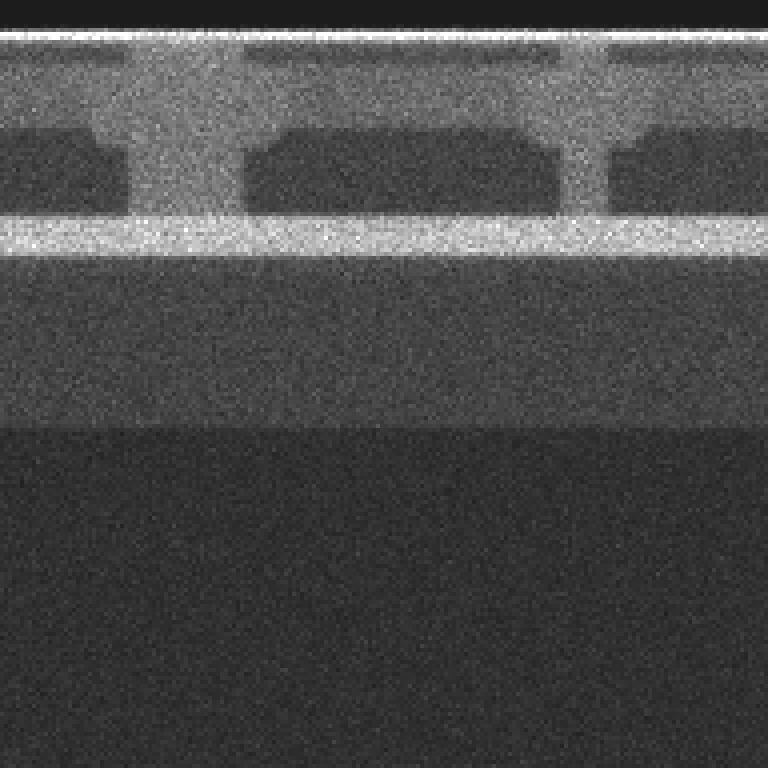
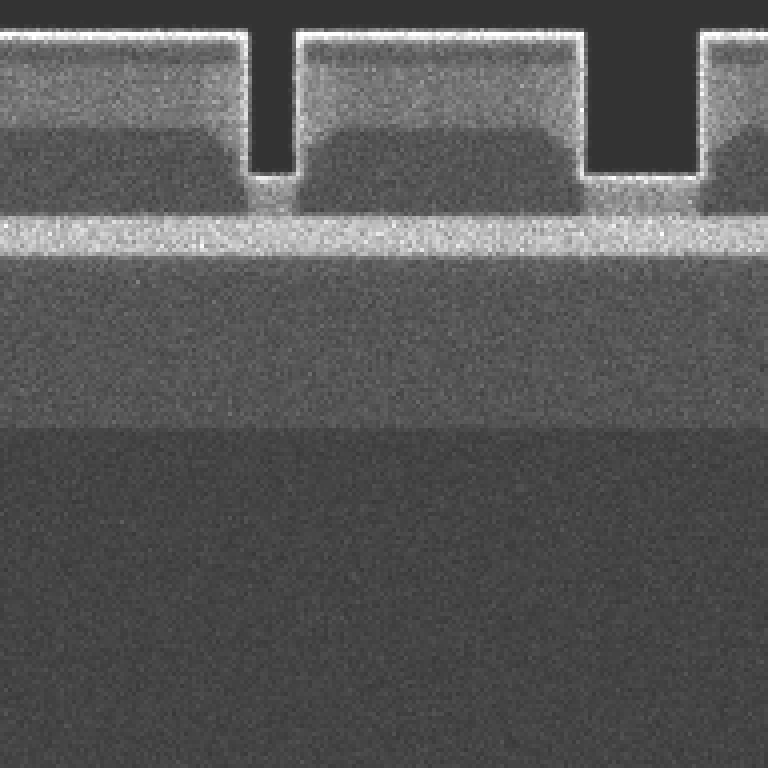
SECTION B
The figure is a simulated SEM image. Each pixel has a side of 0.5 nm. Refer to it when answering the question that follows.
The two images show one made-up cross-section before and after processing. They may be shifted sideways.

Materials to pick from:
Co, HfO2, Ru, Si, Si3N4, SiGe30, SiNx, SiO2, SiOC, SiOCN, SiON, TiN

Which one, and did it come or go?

Ru - removed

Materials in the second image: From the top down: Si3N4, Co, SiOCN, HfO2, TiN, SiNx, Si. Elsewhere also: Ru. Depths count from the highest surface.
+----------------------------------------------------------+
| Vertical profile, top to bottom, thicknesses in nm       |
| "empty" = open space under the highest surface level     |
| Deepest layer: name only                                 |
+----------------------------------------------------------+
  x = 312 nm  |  empty 72, Ru 20, HfO2 20, TiN 10, SiNx 76, Si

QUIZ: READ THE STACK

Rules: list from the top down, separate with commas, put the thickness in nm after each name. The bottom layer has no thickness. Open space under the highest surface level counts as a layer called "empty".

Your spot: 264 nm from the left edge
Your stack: Si3N4 16, Co 32, SiOCN 44, HfO2 20, TiN 10, SiNx 76, Si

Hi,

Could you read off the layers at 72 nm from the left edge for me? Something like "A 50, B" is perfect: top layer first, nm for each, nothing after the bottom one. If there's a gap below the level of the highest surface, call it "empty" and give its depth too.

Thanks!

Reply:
Si3N4 16, Co 32, SiOCN 44, HfO2 20, TiN 10, SiNx 76, Si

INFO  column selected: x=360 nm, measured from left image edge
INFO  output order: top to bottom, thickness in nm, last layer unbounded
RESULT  Si3N4 16, Ru 42, SiOCN 34, HfO2 20, TiN 10, SiNx 76, Si